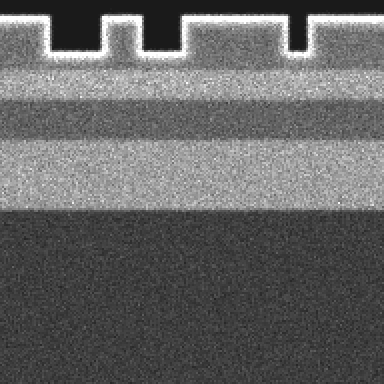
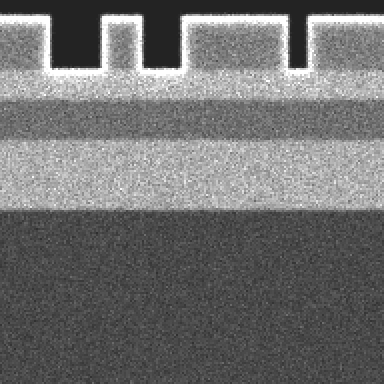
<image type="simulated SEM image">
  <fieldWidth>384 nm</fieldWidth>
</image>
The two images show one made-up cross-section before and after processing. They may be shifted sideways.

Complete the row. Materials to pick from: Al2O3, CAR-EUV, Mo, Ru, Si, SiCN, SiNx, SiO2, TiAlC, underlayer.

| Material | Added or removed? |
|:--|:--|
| underlayer | removed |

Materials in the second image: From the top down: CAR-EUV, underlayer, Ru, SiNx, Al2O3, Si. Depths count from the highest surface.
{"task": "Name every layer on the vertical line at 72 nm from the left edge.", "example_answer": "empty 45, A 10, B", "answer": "empty 54, Ru 30, SiNx 40, Al2O3 70, Si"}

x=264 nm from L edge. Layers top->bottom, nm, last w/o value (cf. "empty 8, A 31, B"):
CAR-EUV 36, underlayer 18, Ru 30, SiNx 40, Al2O3 70, Si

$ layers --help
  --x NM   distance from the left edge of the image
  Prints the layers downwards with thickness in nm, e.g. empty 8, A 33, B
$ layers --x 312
CAR-EUV 36, underlayer 18, Ru 30, SiNx 40, Al2O3 70, Si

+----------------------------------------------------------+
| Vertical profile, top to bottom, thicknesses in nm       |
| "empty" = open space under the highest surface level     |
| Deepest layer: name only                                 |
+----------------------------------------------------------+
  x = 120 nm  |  CAR-EUV 36, underlayer 18, Ru 30, SiNx 40, Al2O3 70, Si